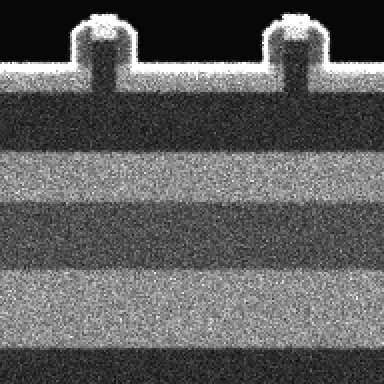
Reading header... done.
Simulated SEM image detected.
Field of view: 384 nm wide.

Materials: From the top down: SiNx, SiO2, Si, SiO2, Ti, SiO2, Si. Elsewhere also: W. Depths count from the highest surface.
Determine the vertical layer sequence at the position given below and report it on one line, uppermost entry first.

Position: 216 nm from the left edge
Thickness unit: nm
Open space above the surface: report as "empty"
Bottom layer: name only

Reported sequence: empty 48, SiO2 28, Si 60, SiO2 50, Ti 68, SiO2 78, Si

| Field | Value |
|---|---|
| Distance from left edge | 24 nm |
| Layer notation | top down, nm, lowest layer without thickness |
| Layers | empty 48, SiO2 28, Si 60, SiO2 50, Ti 68, SiO2 78, Si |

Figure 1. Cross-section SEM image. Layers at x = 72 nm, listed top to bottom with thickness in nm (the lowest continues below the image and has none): empty 16, SiNx 32, SiO2 28, Si 60, SiO2 50, Ti 68, SiO2 78, Si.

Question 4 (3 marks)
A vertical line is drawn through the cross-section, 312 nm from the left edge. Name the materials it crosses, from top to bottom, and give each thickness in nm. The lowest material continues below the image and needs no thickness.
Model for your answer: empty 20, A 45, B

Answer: empty 6, SiNx 42, SiO2 28, Si 60, SiO2 50, Ti 68, SiO2 78, Si